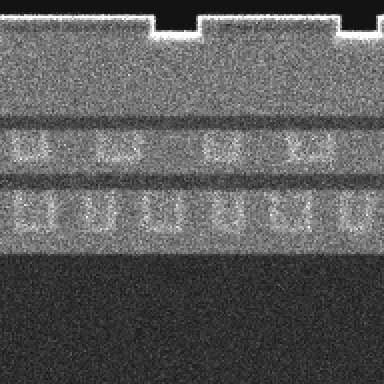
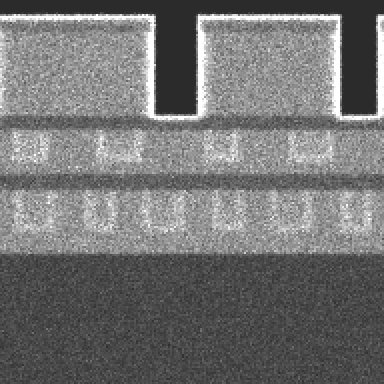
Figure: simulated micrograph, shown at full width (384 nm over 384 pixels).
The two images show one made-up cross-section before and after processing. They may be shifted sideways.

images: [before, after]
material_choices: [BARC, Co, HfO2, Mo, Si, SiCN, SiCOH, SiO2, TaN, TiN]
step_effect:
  removed: SiO2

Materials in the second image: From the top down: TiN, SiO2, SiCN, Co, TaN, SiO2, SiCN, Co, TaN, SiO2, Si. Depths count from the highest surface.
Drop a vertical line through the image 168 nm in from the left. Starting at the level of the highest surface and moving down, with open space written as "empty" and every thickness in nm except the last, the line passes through empty 100, SiCN 14, SiO2 44, SiCN 16, Co 34, TaN 8, SiO2 22, Si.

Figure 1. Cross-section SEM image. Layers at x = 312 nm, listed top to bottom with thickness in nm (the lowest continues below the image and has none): TiN 16, SiO2 84, SiCN 14, Co 24, TaN 8, SiO2 12, SiCN 16, SiO2 64, Si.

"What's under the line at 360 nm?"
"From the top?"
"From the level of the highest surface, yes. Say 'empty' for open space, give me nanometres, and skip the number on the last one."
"empty 100, SiCN 14, SiO2 44, SiCN 16, Co 34, TaN 8, SiO2 22, Si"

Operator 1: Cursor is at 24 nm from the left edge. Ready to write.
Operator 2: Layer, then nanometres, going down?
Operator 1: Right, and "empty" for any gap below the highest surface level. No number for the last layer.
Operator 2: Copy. TiN 16, SiO2 84, SiCN 14, Co 24, TaN 8, SiO2 12, SiCN 16, Co 34, TaN 8, SiO2 22, Si